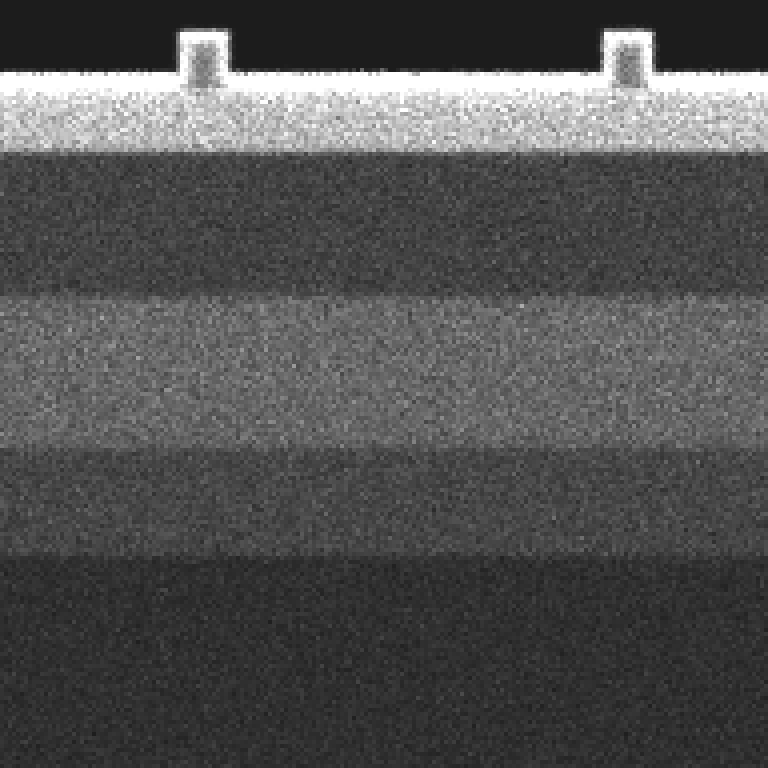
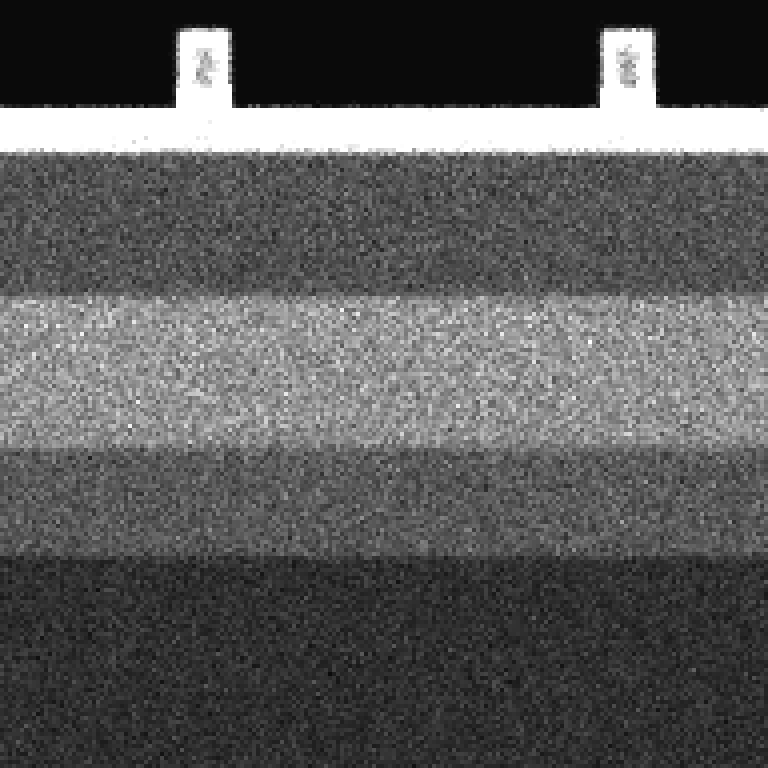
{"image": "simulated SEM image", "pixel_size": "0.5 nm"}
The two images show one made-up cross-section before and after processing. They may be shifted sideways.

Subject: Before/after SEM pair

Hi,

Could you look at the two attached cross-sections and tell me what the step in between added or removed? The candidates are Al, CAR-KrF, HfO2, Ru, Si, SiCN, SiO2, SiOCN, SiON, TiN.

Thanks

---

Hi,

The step removed HfO2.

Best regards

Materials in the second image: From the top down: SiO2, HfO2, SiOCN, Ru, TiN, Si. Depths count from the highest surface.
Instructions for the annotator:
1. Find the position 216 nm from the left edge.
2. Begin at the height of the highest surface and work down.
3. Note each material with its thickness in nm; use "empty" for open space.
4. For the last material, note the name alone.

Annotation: empty 40, HfO2 20, SiOCN 72, Ru 76, TiN 54, Si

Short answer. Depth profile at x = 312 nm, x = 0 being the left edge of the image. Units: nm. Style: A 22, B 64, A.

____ SiO2 28, HfO2 32, SiOCN 72, Ru 76, TiN 54, Si